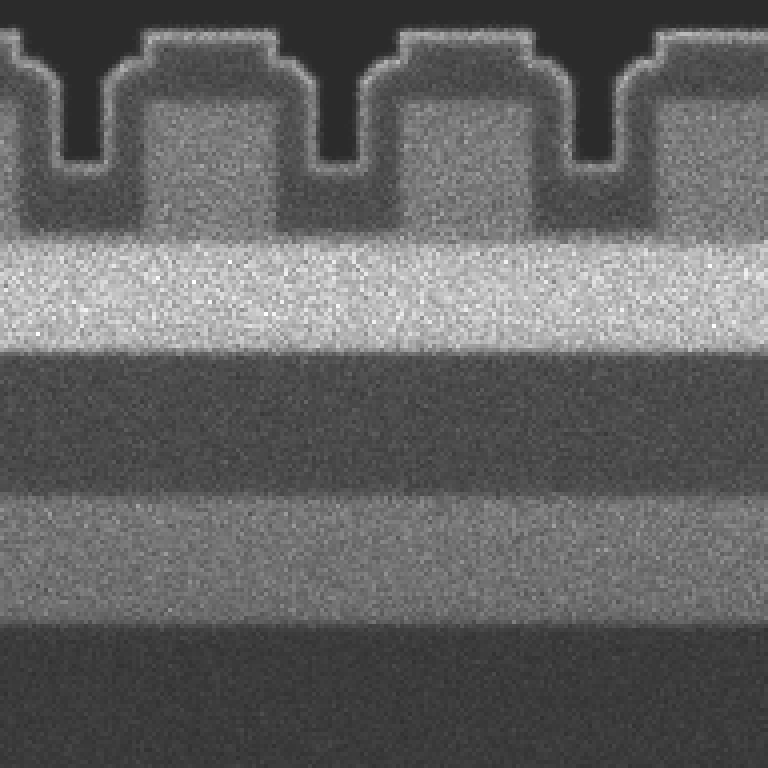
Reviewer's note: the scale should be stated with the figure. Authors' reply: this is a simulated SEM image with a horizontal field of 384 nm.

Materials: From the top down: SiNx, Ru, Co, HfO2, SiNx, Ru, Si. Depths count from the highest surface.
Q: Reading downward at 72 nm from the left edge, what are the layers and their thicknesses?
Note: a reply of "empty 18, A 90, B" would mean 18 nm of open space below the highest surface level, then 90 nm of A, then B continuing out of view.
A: SiNx 34, Ru 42, Co 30, HfO2 54, SiNx 72, Ru 64, Si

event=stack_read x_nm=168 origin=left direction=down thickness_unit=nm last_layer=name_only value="empty 66, SiNx 34, Co 6, HfO2 54, SiNx 72, Ru 64, Si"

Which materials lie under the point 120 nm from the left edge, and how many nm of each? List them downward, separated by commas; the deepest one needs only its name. SiNx 34, Ru 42, Co 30, HfO2 54, SiNx 72, Ru 64, Si